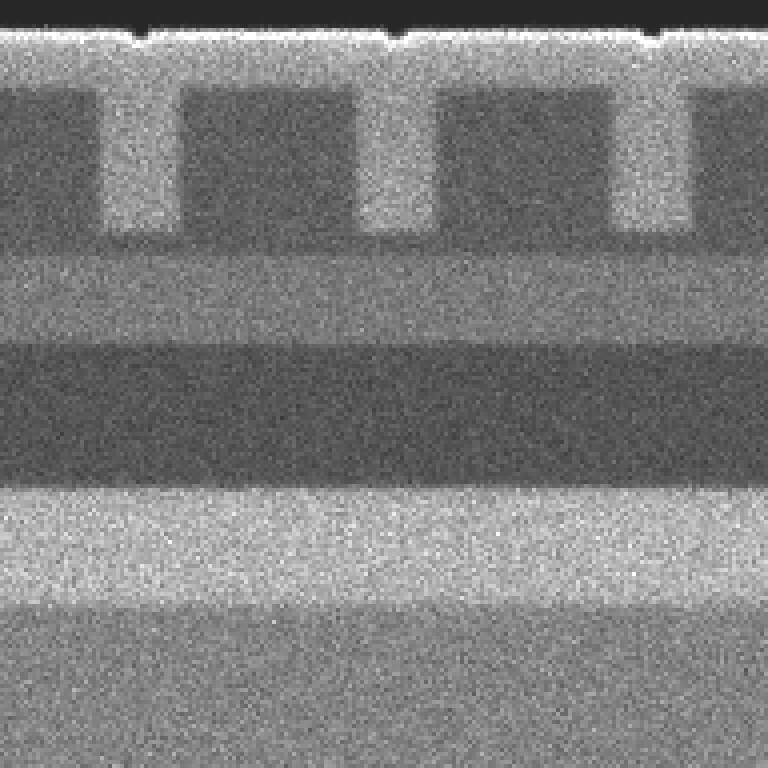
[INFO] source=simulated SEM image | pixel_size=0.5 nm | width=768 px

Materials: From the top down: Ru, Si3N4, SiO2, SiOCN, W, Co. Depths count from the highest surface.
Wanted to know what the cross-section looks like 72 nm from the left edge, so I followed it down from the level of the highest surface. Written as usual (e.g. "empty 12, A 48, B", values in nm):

empty 4, Ru 96, Si3N4 12, SiO2 44, SiOCN 72, W 58, Co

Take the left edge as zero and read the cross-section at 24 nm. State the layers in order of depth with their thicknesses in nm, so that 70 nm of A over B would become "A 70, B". Ru 28, Si3N4 84, SiO2 44, SiOCN 72, W 58, Co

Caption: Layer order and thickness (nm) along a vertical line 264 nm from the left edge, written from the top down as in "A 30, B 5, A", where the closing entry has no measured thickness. Ru 28, Si3N4 84, SiO2 44, SiOCN 72, W 58, Co